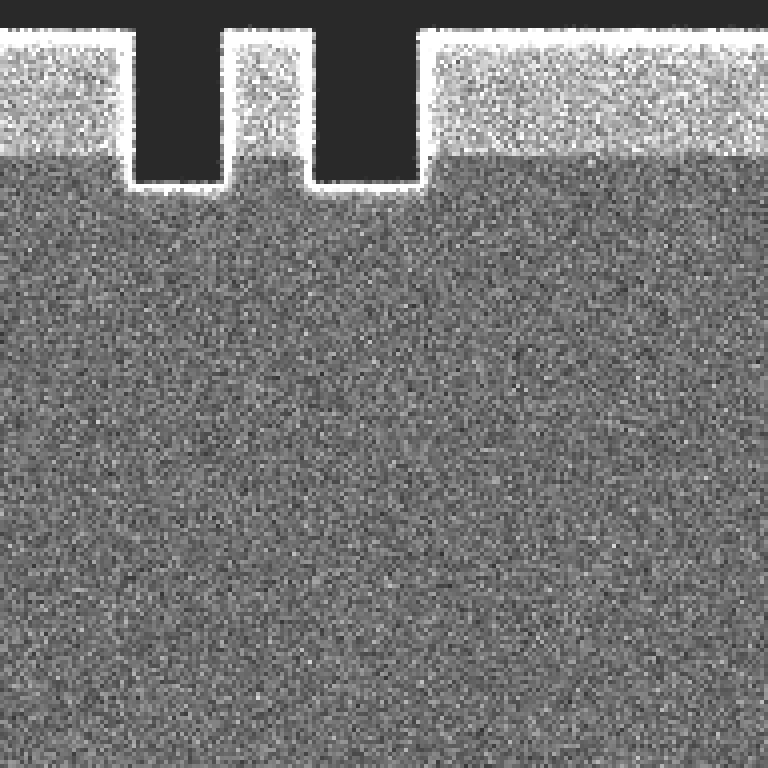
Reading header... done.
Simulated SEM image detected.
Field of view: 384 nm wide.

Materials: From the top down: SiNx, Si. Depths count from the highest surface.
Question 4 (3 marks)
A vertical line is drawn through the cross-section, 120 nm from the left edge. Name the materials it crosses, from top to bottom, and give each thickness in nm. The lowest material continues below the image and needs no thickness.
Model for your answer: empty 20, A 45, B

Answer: SiNx 62, Si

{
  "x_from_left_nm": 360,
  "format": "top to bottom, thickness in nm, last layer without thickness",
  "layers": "SiNx 62, Si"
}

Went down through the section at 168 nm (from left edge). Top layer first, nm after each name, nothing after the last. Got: empty 76, Si